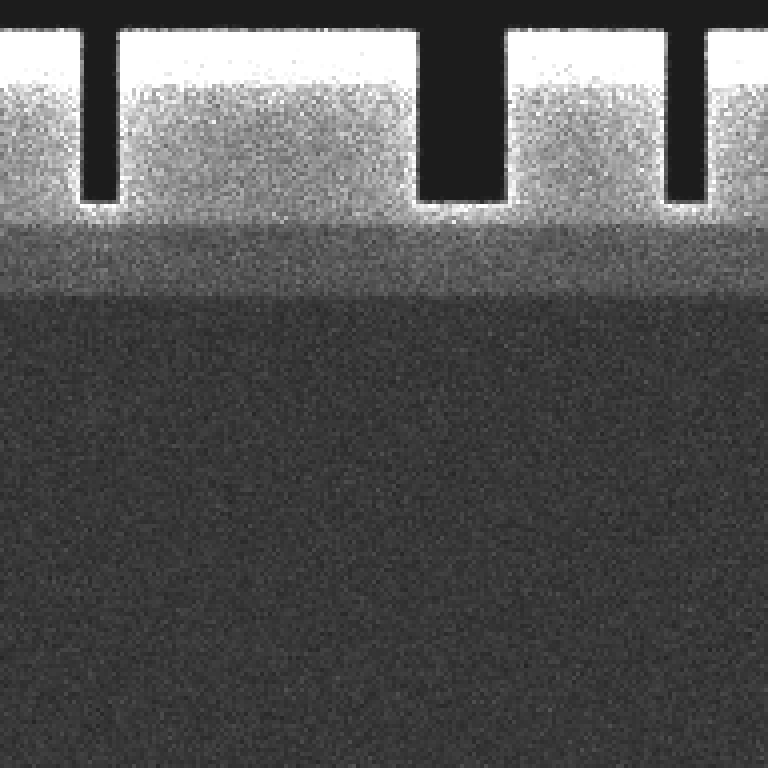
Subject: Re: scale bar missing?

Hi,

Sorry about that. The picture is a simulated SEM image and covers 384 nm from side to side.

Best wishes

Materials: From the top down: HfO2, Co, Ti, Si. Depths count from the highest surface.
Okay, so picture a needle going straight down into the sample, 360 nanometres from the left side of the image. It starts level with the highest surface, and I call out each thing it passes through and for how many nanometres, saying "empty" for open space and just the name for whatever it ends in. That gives HfO2 26, Co 70, Ti 36, Si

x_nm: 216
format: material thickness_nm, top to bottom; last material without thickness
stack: empty 86, Co 10, Ti 36, Si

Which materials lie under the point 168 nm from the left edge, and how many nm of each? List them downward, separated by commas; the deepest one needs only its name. HfO2 26, Co 70, Ti 36, Si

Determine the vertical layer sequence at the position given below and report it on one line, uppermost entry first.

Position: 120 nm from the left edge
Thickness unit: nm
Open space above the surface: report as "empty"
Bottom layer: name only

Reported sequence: HfO2 26, Co 70, Ti 36, Si